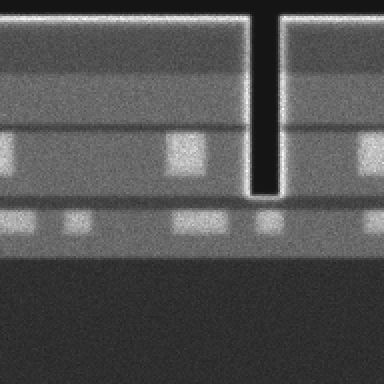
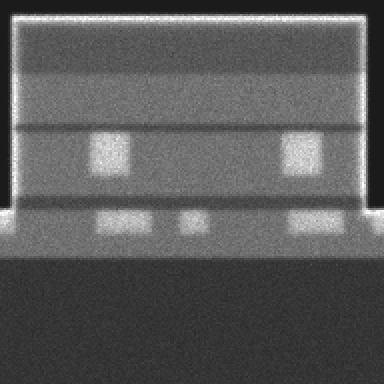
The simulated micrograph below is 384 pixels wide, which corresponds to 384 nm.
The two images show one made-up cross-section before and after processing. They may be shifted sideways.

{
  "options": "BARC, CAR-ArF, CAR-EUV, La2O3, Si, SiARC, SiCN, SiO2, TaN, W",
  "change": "removed",
  "material": "SiCN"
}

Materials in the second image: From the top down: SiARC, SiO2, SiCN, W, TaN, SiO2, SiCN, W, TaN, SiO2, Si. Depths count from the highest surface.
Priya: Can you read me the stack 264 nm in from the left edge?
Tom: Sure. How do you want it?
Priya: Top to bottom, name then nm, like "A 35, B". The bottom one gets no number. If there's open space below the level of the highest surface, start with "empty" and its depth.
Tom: SiARC 58, SiO2 50, SiCN 8, SiO2 64, SiCN 14, SiO2 48, Si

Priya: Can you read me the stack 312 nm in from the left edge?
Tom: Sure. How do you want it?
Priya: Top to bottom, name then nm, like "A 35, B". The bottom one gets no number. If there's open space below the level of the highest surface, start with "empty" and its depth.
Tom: SiARC 58, SiO2 50, SiCN 8, W 38, TaN 6, SiO2 20, SiCN 14, W 18, TaN 6, SiO2 24, Si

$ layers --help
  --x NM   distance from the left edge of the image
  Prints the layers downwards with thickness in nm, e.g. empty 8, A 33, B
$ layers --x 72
SiARC 58, SiO2 50, SiCN 8, SiO2 64, SiCN 14, SiO2 48, Si